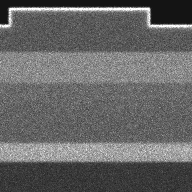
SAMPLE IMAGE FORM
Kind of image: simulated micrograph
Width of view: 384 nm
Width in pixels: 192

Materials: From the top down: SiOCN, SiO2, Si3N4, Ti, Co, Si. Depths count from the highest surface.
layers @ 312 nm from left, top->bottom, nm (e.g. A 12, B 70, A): empty 34, SiOCN 54, SiO2 62, Si3N4 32, Ti 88, Co 38, Si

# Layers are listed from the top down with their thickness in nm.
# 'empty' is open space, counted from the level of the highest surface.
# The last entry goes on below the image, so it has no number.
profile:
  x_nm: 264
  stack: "SiOCN 88, SiO2 62, Si3N4 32, Ti 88, Co 38, Si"